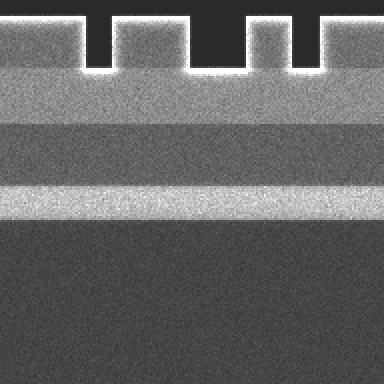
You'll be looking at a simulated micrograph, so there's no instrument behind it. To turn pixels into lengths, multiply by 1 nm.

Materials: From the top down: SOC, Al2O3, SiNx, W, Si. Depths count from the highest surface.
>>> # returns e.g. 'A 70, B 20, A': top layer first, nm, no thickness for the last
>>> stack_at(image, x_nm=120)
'SOC 52, Al2O3 56, SiNx 62, W 34, Si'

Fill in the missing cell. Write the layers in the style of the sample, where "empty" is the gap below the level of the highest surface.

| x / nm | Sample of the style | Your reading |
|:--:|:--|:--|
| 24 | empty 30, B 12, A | SOC 52, Al2O3 56, SiNx 62, W 34, Si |